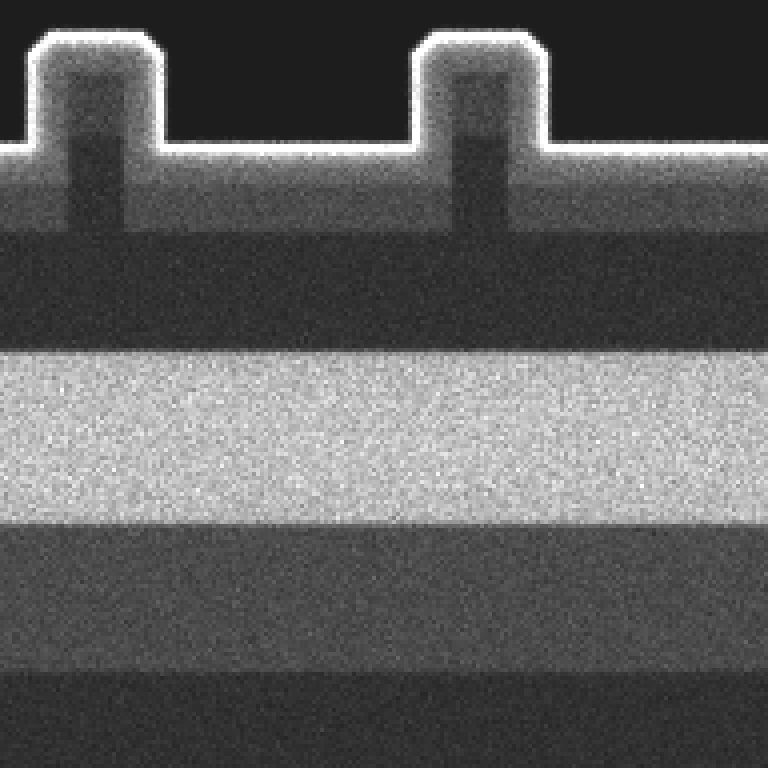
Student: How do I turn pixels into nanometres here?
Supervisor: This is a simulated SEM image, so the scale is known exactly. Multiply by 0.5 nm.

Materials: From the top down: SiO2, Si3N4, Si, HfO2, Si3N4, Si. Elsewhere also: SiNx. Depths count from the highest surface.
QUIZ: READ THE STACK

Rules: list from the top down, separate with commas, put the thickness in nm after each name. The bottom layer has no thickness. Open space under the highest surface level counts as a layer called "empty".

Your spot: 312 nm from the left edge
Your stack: empty 56, SiO2 20, Si3N4 24, Si 60, HfO2 86, Si3N4 74, Si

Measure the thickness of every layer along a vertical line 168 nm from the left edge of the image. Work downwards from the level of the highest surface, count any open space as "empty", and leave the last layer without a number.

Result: empty 56, SiO2 20, Si3N4 24, Si 60, HfO2 86, Si3N4 74, Si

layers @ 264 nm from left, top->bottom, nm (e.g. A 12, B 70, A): empty 2, SiO2 74, Si3N4 24, Si 60, HfO2 86, Si3N4 74, Si